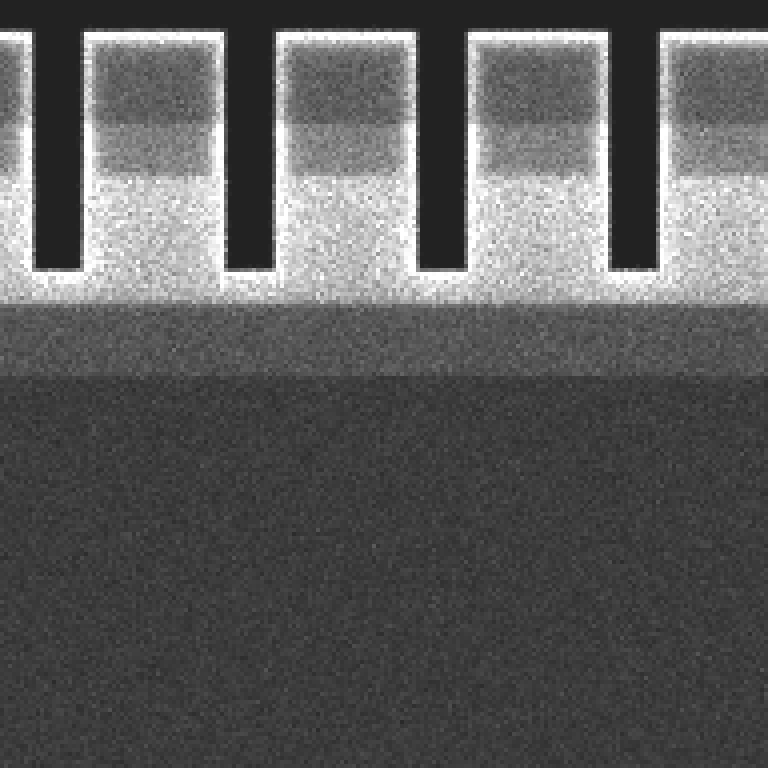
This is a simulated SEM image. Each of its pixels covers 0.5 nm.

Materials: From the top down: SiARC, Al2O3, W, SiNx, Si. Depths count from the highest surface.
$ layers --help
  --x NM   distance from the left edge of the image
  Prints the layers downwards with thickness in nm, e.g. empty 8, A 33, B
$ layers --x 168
SiARC 46, Al2O3 26, W 64, SiNx 36, Si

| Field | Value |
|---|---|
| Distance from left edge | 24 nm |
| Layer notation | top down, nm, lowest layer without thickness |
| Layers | empty 120, W 16, SiNx 36, Si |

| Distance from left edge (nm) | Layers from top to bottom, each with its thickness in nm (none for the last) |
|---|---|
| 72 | SiARC 46, Al2O3 26, W 64, SiNx 36, Si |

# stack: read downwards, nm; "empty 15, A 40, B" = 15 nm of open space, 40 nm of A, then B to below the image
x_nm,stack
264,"SiARC 46, Al2O3 26, W 64, SiNx 36, Si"